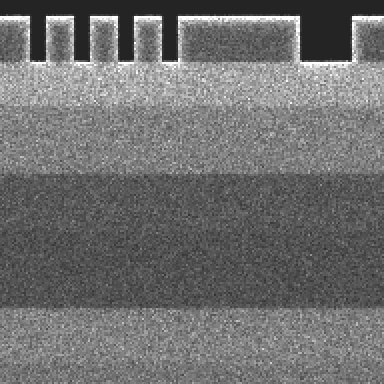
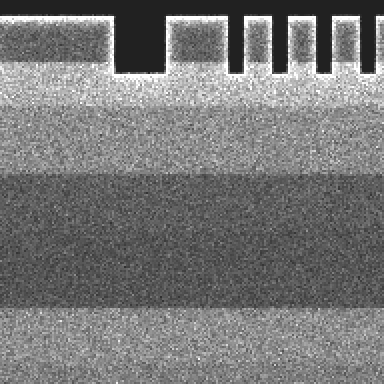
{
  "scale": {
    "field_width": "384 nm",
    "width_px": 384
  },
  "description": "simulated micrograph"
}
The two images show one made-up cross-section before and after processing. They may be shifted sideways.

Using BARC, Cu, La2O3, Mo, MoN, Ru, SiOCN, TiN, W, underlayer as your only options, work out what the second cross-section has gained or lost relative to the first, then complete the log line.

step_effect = removed W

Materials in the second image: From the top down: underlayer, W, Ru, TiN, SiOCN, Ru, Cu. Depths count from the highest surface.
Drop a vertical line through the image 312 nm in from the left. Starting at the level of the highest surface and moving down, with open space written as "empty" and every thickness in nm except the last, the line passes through underlayer 46, W 44, Ru 68, TiN 58, SiOCN 76, Ru 56, Cu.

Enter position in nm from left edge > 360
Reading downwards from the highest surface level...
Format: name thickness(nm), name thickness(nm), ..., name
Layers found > empty 58, W 32, Ru 68, TiN 58, SiOCN 76, Ru 56, Cu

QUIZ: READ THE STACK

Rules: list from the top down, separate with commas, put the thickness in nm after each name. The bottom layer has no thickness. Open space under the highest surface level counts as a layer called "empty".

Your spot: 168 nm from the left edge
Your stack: underlayer 46, W 44, Ru 68, TiN 58, SiOCN 76, Ru 56, Cu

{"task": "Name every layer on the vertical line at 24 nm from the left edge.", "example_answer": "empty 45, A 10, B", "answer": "underlayer 46, W 44, Ru 68, TiN 58, SiOCN 76, Ru 56, Cu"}